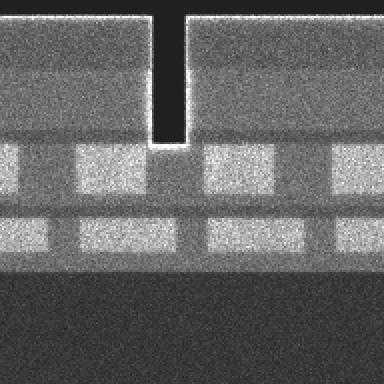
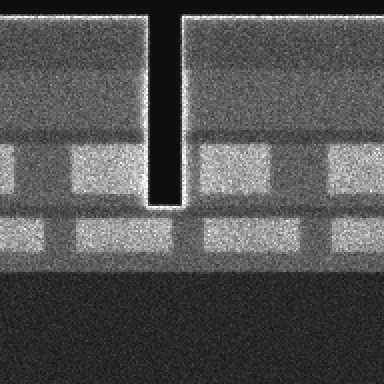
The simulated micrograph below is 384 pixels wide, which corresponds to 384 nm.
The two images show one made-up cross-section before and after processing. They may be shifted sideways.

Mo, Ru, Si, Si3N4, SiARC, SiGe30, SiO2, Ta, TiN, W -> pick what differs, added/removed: SiO2 removed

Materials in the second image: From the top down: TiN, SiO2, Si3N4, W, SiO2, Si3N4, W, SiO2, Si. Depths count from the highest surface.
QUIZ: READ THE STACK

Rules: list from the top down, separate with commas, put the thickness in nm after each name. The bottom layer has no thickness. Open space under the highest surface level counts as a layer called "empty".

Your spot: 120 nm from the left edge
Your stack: TiN 54, SiO2 60, Si3N4 14, W 50, SiO2 12, Si3N4 12, W 34, SiO2 20, Si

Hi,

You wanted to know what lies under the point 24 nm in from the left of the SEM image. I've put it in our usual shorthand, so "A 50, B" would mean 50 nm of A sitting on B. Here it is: TiN 54, SiO2 60, Si3N4 14, SiO2 62, Si3N4 12, W 34, SiO2 20, Si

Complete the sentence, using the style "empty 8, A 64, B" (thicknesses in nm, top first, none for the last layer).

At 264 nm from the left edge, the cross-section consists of TiN 54, SiO2 60, Si3N4 14, W 50, SiO2 12, Si3N4 12, W 34, SiO2 20, Si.